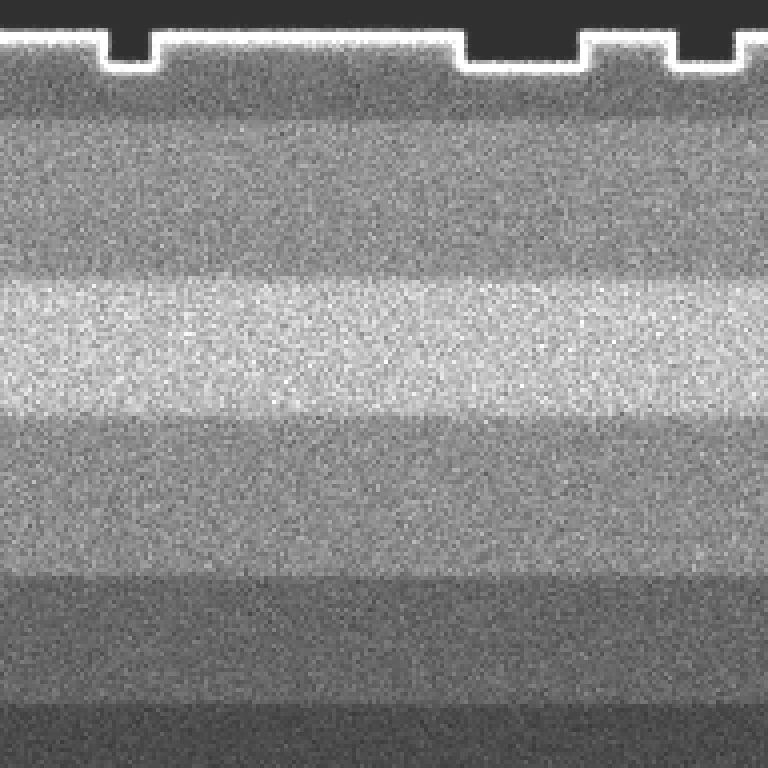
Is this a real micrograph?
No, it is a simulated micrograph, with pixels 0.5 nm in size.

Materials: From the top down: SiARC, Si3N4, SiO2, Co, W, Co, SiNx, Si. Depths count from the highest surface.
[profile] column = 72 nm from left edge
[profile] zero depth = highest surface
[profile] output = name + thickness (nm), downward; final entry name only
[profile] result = empty 16, Si3N4 28, SiO2 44, Co 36, W 68, Co 80, SiNx 64, Si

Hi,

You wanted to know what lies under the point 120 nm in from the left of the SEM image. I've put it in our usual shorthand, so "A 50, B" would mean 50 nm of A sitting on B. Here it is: SiARC 16, Si3N4 28, SiO2 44, Co 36, W 68, Co 80, SiNx 64, Si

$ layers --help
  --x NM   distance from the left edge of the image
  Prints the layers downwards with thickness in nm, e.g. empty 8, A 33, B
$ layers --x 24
SiARC 16, Si3N4 28, SiO2 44, Co 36, W 68, Co 80, SiNx 64, Si